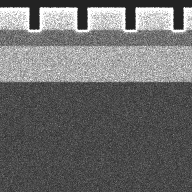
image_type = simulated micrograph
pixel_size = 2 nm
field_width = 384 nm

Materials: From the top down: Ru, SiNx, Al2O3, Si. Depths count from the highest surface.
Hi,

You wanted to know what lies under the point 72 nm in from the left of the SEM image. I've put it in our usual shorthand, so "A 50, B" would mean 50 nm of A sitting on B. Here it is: empty 44, SiNx 32, Al2O3 72, Si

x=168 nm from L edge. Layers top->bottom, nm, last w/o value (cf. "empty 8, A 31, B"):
empty 44, SiNx 32, Al2O3 72, Si